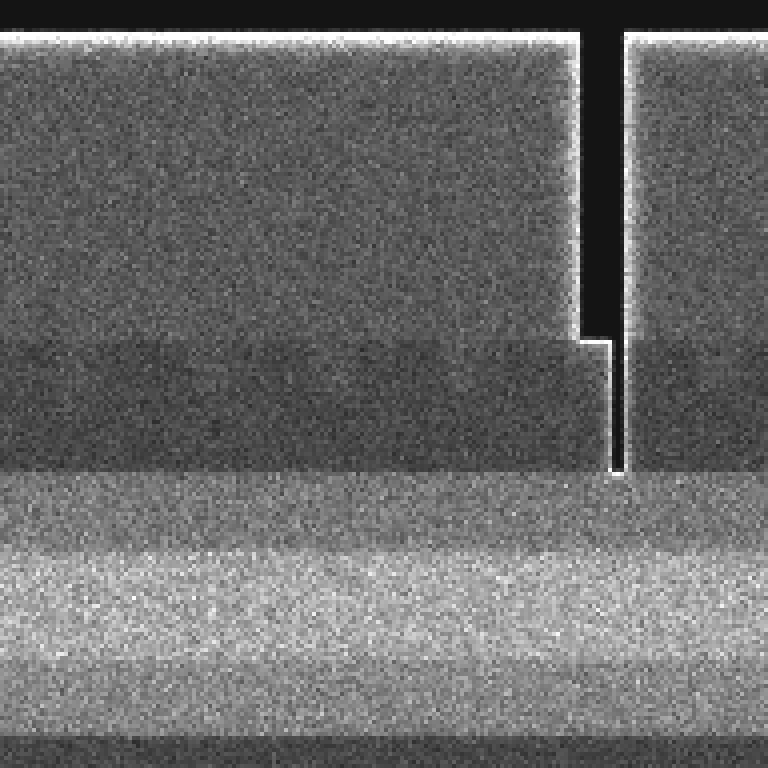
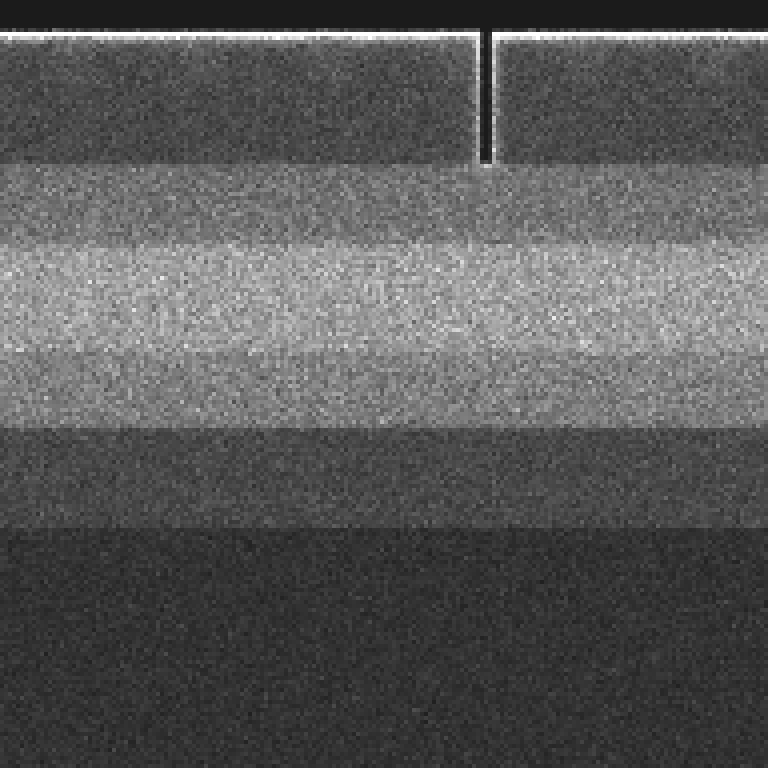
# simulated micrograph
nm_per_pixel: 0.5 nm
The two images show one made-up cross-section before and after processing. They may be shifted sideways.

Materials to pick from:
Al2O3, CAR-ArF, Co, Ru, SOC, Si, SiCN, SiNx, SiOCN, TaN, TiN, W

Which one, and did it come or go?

SOC - removed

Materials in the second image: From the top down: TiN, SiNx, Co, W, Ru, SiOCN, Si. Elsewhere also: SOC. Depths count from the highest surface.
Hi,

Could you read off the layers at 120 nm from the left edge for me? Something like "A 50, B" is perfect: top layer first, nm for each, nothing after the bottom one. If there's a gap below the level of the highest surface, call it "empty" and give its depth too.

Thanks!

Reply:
SiNx 66, Co 40, W 54, Ru 38, SiOCN 50, Si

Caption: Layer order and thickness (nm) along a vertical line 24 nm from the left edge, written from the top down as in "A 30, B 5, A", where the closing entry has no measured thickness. SiNx 66, Co 40, W 54, Ru 38, SiOCN 50, Si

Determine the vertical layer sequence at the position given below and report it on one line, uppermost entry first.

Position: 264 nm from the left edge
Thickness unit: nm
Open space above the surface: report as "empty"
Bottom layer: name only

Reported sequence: SiNx 66, Co 40, W 54, Ru 38, SiOCN 50, Si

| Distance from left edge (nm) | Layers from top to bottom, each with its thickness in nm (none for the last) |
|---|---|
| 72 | SiNx 66, Co 40, W 54, Ru 38, SiOCN 50, Si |